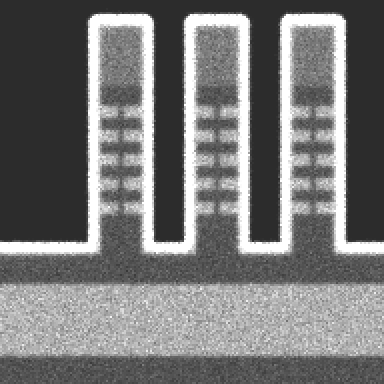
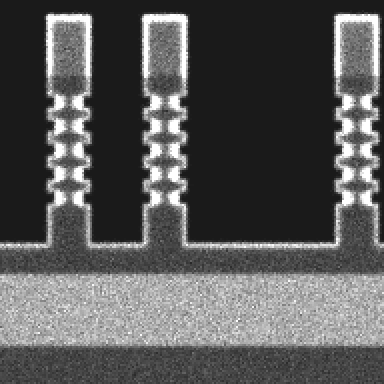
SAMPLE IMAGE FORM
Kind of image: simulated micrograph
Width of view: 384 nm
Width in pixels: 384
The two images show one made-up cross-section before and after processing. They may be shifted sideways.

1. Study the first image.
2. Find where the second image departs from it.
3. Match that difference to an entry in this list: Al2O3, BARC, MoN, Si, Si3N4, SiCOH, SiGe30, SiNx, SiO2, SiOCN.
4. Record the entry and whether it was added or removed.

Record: Al2O3 / removed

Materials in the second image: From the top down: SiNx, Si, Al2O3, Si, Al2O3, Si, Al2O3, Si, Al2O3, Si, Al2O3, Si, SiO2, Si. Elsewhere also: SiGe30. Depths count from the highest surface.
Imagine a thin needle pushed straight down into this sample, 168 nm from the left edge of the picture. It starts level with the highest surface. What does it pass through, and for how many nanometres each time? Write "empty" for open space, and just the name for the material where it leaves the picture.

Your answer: SiNx 60, Si 20, Al2O3 12, Si 12, Al2O3 12, Si 12, Al2O3 12, Si 12, Al2O3 12, Si 12, Al2O3 12, Si 70, SiO2 72, Si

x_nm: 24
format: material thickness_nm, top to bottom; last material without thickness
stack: empty 228, Si 30, SiO2 72, Si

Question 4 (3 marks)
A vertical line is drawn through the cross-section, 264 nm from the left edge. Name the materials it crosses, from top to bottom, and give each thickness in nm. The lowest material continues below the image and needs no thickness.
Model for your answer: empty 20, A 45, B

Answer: empty 228, Si 30, SiO2 72, Si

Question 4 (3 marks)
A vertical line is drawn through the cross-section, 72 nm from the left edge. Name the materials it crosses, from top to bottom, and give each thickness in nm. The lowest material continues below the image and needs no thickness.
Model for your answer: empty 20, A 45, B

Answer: SiNx 60, Si 20, Al2O3 12, Si 12, Al2O3 12, Si 12, Al2O3 12, Si 12, Al2O3 12, Si 12, Al2O3 12, Si 70, SiO2 72, Si